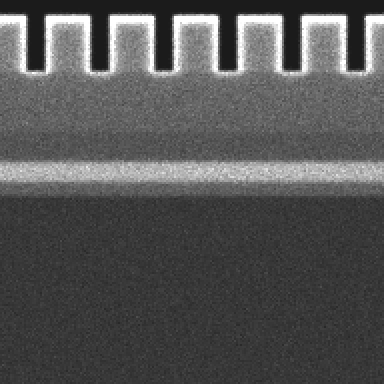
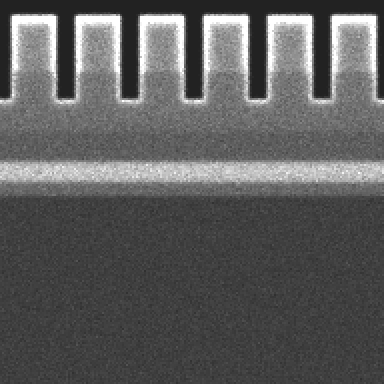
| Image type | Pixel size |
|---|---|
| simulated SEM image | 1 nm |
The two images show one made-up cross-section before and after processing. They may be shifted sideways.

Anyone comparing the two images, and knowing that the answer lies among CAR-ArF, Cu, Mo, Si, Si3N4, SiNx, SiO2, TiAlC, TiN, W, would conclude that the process removed TiN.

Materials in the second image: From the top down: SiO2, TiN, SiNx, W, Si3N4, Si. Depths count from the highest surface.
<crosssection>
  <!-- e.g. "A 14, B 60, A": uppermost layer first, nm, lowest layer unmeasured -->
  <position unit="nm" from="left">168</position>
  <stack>SiO2 56, TiN 60, SiNx 30, W 20, Si3N4 14, Si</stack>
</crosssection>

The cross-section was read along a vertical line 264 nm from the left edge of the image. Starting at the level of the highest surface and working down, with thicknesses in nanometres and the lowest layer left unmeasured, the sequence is empty 84, TiN 32, SiNx 30, W 20, Si3N4 14, Si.